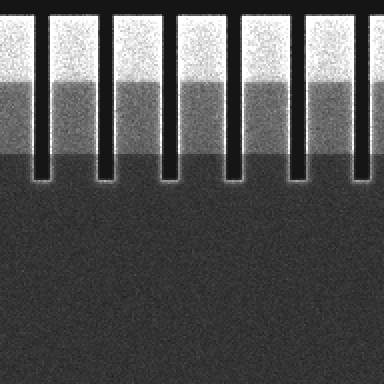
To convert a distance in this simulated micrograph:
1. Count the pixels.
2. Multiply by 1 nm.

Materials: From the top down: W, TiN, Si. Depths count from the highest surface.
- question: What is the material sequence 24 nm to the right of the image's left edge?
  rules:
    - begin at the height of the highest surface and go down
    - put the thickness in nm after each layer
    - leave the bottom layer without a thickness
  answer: W 66, TiN 72, Si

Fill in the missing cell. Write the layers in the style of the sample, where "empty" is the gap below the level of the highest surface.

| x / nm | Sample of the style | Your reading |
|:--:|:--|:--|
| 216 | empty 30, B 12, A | W 66, TiN 72, Si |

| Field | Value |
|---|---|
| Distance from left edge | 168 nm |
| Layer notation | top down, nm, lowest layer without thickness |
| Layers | empty 164, Si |